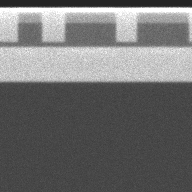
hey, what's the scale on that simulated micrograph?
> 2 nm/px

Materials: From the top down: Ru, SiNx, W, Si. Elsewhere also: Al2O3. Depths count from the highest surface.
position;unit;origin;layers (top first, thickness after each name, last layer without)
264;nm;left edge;Ru 68, SiNx 10, W 70, Si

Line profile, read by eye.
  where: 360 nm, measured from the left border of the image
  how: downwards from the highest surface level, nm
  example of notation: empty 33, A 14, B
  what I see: Al2O3 30, SiNx 48, W 70, Si